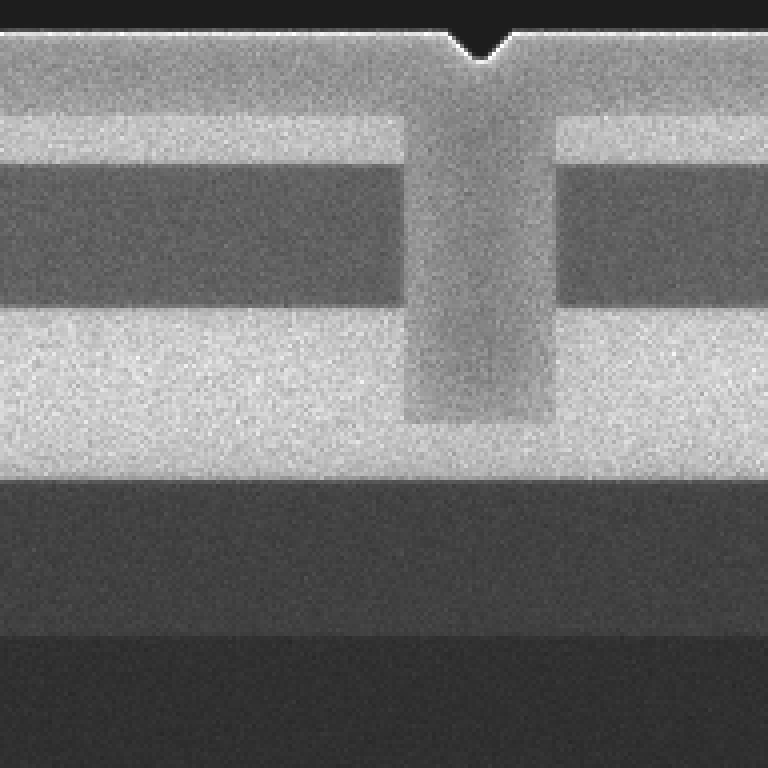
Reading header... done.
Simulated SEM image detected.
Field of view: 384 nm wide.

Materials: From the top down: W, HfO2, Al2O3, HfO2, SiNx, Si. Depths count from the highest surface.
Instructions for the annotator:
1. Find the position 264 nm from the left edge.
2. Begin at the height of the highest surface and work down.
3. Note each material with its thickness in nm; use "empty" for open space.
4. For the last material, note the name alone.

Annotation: W 196, HfO2 28, SiNx 78, Si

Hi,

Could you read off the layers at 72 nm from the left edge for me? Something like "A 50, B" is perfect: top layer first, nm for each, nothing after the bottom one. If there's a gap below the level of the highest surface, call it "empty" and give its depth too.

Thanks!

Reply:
W 42, HfO2 24, Al2O3 72, HfO2 86, SiNx 78, Si